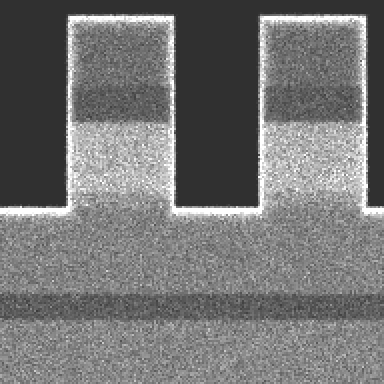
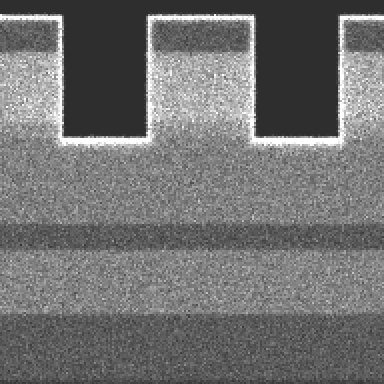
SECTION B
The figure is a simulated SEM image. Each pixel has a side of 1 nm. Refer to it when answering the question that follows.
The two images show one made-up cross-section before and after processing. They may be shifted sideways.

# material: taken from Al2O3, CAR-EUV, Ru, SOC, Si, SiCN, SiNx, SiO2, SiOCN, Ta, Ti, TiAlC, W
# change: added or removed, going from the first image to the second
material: SOC
change: removed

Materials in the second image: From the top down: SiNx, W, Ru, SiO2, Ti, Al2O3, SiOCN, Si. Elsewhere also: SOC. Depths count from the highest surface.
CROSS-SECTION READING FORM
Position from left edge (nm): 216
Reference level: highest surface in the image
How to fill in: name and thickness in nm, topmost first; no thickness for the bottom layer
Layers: SiNx 36, W 70, Ru 16, SiO2 86, Ti 26, Al2O3 64, SiOCN 66, Si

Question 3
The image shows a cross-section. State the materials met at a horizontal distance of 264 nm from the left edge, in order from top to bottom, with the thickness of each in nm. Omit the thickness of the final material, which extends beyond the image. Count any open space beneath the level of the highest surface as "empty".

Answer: empty 122, SiO2 86, Ti 26, Al2O3 64, SiOCN 66, Si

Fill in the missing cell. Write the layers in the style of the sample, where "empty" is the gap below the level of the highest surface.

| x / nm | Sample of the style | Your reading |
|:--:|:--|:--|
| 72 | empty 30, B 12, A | empty 122, SiO2 86, Ti 26, Al2O3 64, SiOCN 66, Si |